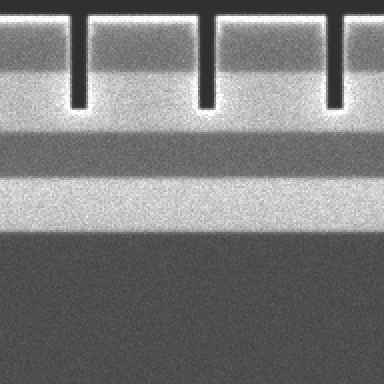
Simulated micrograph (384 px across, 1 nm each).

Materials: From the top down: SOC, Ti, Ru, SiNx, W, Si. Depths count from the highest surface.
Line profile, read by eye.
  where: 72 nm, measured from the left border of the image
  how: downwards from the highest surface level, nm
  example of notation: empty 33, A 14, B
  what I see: empty 94, Ru 22, SiNx 46, W 54, Si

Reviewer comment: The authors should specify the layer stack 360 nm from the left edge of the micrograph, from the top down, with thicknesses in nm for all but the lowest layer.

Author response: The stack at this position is SOC 20, Ti 36, Ru 60, SiNx 46, W 54, Si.